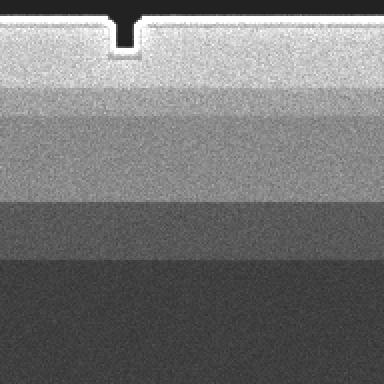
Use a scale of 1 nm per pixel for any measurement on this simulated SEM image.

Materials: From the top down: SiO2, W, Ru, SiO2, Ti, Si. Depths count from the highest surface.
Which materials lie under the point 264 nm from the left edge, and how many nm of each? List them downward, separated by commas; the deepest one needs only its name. SiO2 12, W 60, Ru 28, SiO2 86, Ti 58, Si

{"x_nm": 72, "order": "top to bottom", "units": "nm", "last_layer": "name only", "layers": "SiO2 12, W 60, Ru 28, SiO2 86, Ti 58, Si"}